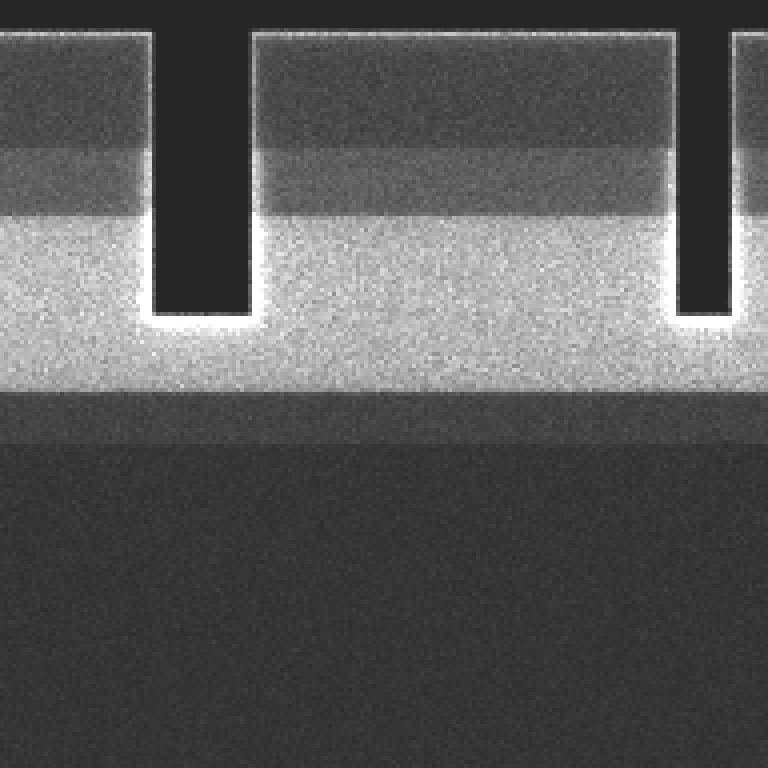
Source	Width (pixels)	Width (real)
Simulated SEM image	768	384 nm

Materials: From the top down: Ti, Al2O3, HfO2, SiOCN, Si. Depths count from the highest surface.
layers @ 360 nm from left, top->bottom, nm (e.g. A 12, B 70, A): empty 142, HfO2 38, SiOCN 26, Si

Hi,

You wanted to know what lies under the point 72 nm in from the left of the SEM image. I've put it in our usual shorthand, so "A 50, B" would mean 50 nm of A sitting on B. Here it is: Ti 58, Al2O3 34, HfO2 88, SiOCN 26, Si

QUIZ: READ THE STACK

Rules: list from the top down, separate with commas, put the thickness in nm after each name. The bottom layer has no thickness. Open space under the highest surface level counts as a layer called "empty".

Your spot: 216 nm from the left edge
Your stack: Ti 58, Al2O3 34, HfO2 88, SiOCN 26, Si